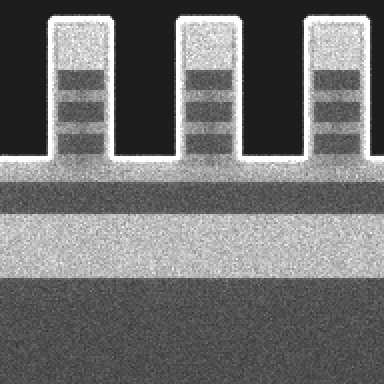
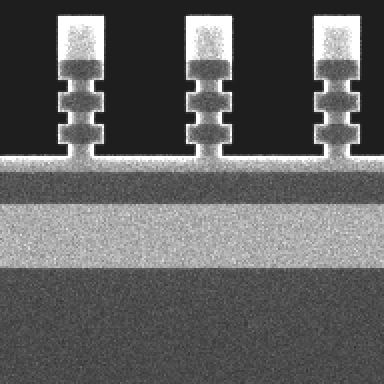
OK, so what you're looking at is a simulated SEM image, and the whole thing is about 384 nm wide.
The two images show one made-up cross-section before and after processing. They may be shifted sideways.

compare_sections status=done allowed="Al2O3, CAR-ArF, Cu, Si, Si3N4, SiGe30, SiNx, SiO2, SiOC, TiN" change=removed material="Si3N4"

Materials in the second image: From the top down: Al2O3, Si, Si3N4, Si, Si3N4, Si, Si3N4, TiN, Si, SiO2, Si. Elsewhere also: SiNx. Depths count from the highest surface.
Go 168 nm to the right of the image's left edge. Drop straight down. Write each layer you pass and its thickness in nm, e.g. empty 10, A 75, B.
empty 140, TiN 16, Si 32, SiO2 64, Si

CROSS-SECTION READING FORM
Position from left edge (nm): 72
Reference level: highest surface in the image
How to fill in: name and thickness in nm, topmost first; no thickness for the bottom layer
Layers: Al2O3 44, Si 20, Si3N4 12, Si 20, Si3N4 12, Si 20, Si3N4 12, TiN 16, Si 32, SiO2 64, Si